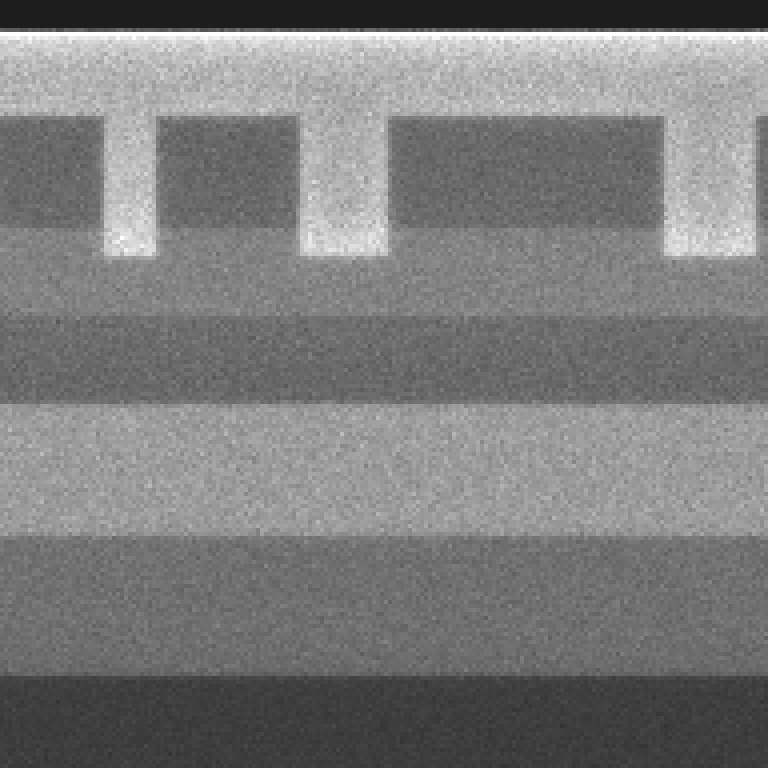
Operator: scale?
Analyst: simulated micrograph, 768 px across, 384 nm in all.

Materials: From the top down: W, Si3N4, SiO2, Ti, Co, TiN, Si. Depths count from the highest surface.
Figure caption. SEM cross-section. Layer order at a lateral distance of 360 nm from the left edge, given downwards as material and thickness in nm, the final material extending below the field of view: W 112, SiO2 30, Ti 44, Co 66, TiN 70, Si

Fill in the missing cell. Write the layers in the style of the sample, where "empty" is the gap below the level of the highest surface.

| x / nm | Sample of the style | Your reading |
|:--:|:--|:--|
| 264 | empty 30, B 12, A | W 42, Si3N4 56, SiO2 44, Ti 44, Co 66, TiN 70, Si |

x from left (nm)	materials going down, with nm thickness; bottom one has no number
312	W 42, Si3N4 56, SiO2 44, Ti 44, Co 66, TiN 70, Si